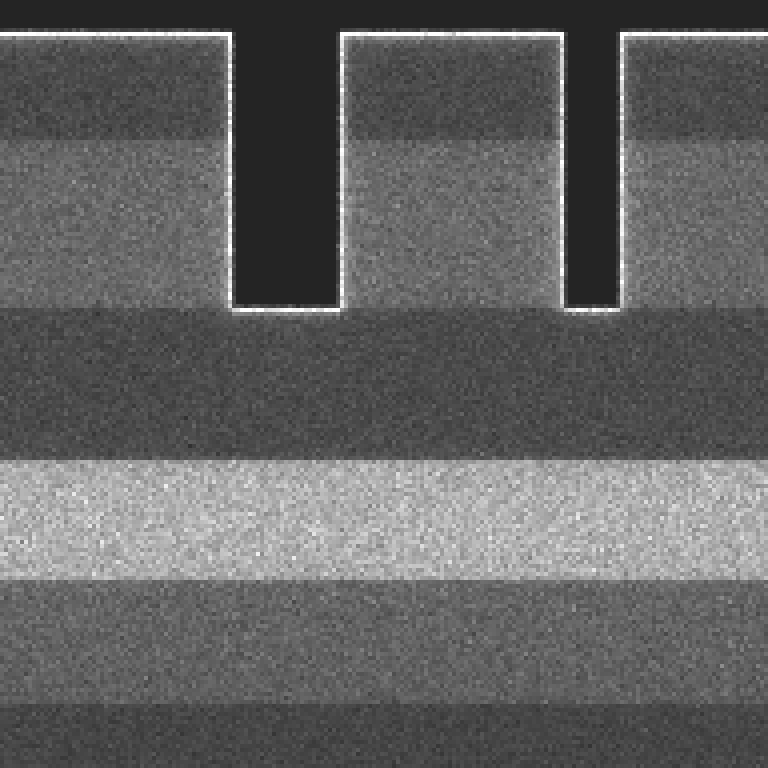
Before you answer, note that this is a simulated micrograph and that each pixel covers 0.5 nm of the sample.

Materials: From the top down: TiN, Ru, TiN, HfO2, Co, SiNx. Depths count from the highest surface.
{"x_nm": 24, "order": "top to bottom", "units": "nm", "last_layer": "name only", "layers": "TiN 54, Ru 84, TiN 76, HfO2 60, Co 62, SiNx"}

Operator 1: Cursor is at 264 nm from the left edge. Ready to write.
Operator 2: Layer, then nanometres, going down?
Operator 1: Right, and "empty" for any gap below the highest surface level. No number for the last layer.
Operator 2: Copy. TiN 54, Ru 84, TiN 76, HfO2 60, Co 62, SiNx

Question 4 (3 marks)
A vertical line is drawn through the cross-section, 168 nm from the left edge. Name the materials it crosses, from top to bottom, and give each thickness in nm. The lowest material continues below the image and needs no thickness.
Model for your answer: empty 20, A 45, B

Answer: empty 138, TiN 76, HfO2 60, Co 62, SiNx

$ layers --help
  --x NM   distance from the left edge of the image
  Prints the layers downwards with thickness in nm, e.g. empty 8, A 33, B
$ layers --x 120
empty 138, TiN 76, HfO2 60, Co 62, SiNx